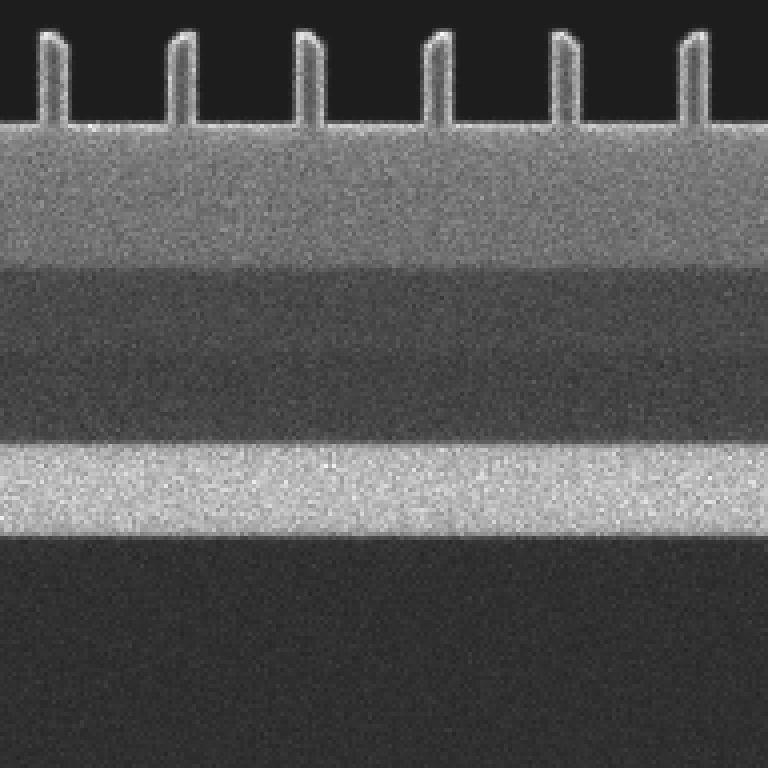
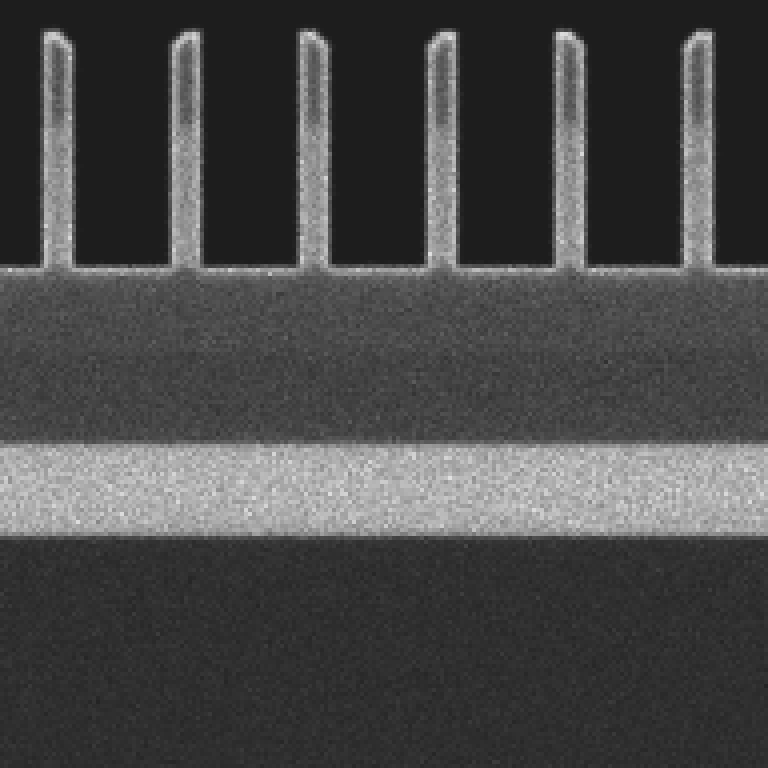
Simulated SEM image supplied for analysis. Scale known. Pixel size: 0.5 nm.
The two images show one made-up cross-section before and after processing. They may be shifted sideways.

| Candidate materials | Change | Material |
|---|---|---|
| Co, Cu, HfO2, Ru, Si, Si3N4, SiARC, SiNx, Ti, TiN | removed | Ru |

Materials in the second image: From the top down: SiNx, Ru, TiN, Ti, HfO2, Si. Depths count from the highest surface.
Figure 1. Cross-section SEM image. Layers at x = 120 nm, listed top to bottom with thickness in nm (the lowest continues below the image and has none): empty 118, TiN 42, Ti 46, HfO2 46, Si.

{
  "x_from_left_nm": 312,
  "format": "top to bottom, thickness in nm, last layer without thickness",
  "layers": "empty 118, TiN 42, Ti 46, HfO2 46, Si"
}